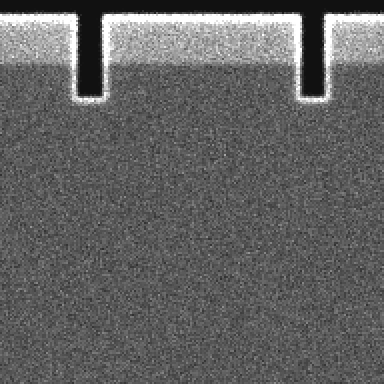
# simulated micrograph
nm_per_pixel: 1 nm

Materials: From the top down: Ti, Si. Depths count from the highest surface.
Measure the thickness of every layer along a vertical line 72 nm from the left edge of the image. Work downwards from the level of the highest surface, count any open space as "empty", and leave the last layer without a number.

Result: Ti 48, Si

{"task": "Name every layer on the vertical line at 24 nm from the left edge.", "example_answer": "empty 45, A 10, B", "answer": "Ti 48, Si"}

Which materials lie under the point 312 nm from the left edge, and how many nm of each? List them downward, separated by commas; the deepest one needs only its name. empty 82, Si